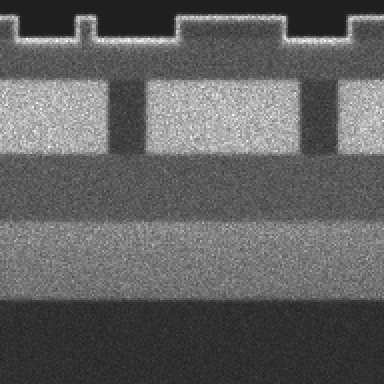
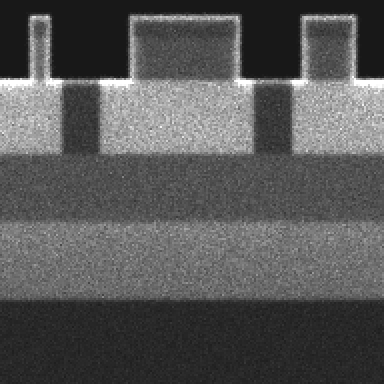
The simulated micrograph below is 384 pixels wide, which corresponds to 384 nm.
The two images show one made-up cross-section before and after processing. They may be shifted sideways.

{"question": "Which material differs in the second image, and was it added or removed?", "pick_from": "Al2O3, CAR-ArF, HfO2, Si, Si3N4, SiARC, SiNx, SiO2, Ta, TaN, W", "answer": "SiO2, removed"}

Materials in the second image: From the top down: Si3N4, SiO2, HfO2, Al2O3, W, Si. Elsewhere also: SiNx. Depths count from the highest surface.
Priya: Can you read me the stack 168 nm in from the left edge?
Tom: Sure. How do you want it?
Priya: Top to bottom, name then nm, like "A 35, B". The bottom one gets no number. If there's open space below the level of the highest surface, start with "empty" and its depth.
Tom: Si3N4 22, SiO2 42, HfO2 74, Al2O3 68, W 78, Si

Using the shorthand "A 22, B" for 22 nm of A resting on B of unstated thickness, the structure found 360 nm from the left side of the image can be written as empty 64, HfO2 74, Al2O3 68, W 78, Si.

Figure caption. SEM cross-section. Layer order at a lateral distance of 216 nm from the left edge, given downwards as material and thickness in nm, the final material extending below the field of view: Si3N4 22, SiO2 42, HfO2 74, Al2O3 68, W 78, Si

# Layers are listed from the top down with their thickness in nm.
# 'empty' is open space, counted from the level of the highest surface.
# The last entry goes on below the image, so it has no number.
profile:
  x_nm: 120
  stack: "empty 64, HfO2 74, Al2O3 68, W 78, Si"